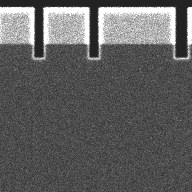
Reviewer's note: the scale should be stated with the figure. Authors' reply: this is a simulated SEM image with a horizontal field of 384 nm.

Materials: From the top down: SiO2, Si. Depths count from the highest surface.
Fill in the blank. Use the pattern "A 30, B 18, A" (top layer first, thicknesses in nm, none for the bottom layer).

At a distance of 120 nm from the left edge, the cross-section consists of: SiO2 72, Si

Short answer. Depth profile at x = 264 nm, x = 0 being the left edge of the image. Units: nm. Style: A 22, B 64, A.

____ SiO2 72, Si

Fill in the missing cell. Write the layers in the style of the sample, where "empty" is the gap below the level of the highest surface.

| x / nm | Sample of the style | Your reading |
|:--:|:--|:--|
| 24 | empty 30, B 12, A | SiO2 72, Si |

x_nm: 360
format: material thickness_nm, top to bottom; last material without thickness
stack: empty 100, Si